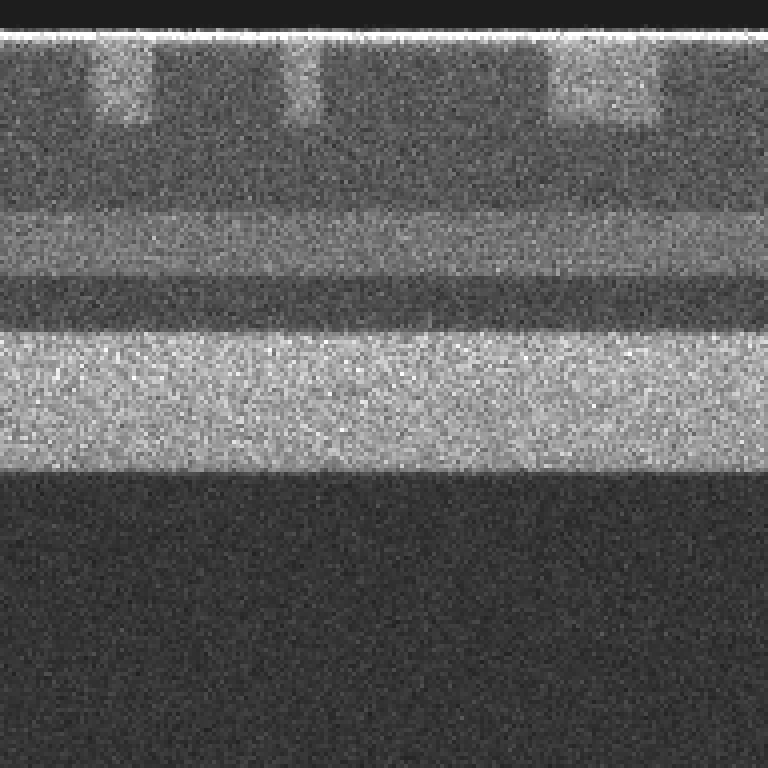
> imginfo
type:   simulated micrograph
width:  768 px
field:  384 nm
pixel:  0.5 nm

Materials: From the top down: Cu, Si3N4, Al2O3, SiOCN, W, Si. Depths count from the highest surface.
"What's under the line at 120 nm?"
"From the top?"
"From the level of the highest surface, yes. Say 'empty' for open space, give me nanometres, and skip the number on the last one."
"Si3N4 90, Al2O3 32, SiOCN 28, W 70, Si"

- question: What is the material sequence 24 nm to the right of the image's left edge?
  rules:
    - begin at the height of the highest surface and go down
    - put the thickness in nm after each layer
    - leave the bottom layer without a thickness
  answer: Si3N4 90, Al2O3 32, SiOCN 28, W 70, Si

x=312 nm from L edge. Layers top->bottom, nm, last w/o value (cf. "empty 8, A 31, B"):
Cu 46, Si3N4 44, Al2O3 32, SiOCN 28, W 70, Si